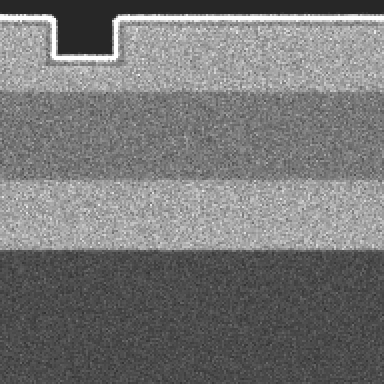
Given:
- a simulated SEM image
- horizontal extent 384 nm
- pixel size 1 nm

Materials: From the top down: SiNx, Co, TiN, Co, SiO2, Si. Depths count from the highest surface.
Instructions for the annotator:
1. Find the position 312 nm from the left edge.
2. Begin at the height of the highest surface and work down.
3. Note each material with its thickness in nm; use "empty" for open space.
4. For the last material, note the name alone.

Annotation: SiNx 10, Co 66, TiN 88, Co 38, SiO2 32, Si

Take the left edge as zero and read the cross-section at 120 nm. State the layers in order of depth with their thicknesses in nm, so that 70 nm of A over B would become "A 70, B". SiNx 50, Co 26, TiN 88, Co 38, SiO2 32, Si